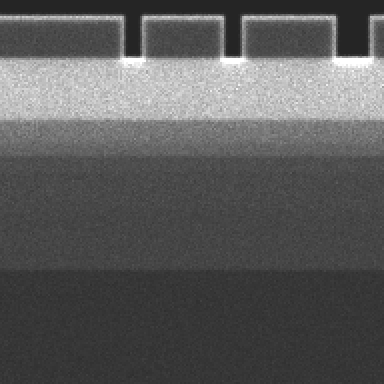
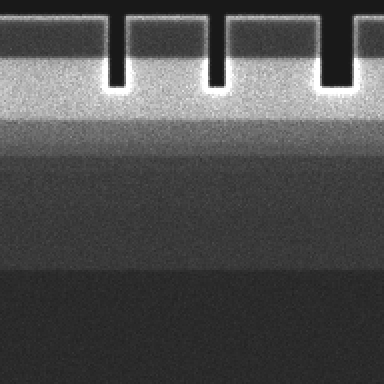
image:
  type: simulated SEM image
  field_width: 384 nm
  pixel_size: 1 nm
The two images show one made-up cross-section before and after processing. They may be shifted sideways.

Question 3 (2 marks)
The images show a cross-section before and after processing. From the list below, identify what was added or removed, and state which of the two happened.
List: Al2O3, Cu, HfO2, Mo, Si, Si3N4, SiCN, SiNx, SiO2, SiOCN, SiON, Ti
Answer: HfO2 was removed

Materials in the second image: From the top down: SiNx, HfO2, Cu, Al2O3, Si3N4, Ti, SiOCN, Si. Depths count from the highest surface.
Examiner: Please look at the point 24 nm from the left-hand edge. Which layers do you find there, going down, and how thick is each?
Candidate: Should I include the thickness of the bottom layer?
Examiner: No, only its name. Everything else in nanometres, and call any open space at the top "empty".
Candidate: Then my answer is SiNx 42, HfO2 62, Cu 24, Al2O3 12, Si3N4 16, Ti 38, SiOCN 60, Si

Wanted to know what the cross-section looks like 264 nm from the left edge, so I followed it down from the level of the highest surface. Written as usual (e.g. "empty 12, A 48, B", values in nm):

SiNx 42, HfO2 62, Cu 24, Al2O3 12, Si3N4 16, Ti 38, SiOCN 60, Si